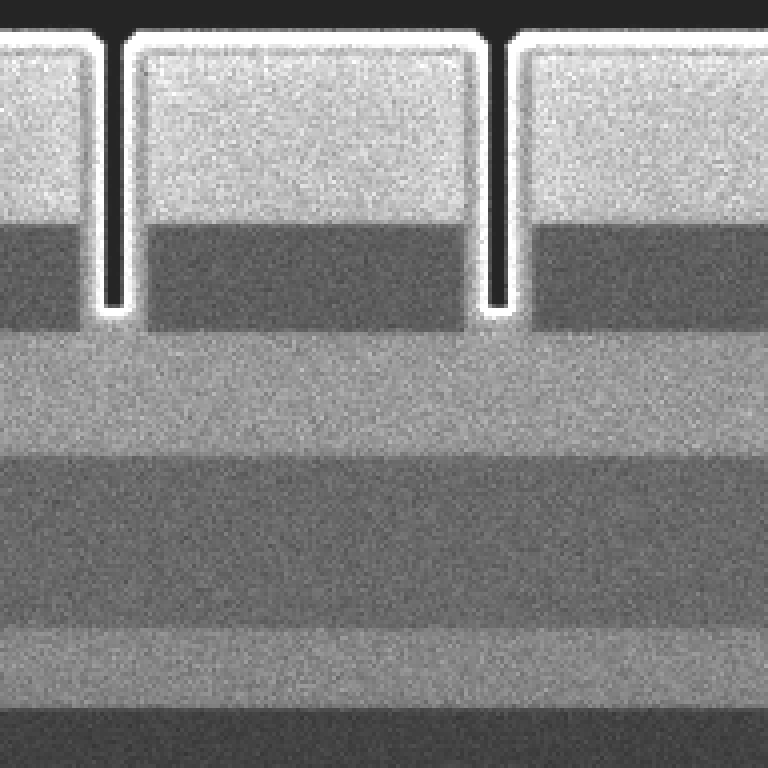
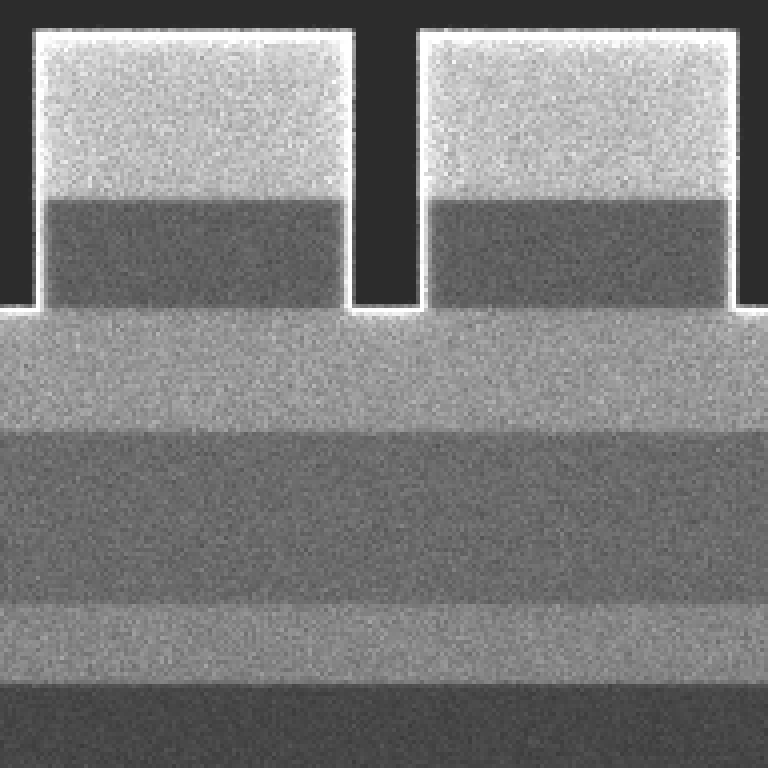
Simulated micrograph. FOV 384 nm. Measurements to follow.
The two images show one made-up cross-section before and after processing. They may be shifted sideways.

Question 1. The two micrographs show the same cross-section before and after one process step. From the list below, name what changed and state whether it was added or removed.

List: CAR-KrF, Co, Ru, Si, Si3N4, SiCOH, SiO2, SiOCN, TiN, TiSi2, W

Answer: SiO2, removed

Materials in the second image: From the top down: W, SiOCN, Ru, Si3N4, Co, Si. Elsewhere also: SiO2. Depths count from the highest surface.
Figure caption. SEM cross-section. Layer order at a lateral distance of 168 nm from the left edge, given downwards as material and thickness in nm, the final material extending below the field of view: W 84, SiOCN 54, Ru 62, Si3N4 86, Co 40, Si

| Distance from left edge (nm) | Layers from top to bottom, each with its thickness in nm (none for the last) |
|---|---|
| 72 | W 84, SiOCN 54, Ru 62, Si3N4 86, Co 40, Si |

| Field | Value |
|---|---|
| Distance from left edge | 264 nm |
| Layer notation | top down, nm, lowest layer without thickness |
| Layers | W 84, SiOCN 54, Ru 62, Si3N4 86, Co 40, Si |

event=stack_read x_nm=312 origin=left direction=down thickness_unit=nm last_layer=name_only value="W 84, SiOCN 54, Ru 62, Si3N4 86, Co 40, Si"